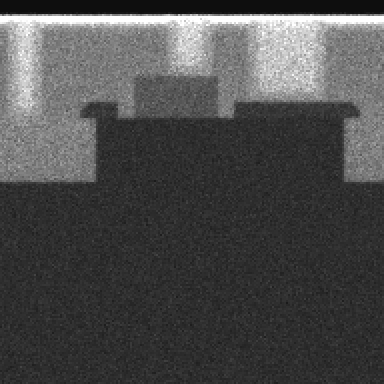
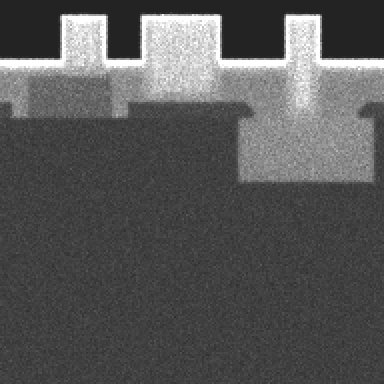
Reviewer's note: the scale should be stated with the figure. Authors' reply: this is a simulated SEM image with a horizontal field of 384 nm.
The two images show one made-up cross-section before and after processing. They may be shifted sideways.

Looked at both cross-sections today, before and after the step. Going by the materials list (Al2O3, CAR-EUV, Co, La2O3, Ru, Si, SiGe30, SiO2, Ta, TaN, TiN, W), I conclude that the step removed SiO2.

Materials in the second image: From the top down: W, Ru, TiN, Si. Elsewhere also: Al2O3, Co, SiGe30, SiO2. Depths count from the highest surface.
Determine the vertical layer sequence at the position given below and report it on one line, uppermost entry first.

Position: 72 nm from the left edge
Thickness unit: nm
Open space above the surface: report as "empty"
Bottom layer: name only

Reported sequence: W 50, Ru 10, TiN 42, Si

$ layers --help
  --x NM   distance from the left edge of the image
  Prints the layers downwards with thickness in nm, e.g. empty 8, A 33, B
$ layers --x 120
empty 44, SiO2 18, Al2O3 40, Si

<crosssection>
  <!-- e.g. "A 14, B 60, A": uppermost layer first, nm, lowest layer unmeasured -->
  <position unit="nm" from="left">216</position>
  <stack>Ru 86, SiGe30 16, Si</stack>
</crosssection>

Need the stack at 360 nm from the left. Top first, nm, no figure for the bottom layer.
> empty 44, SiO2 48, SiGe30 10, Co 64, Si